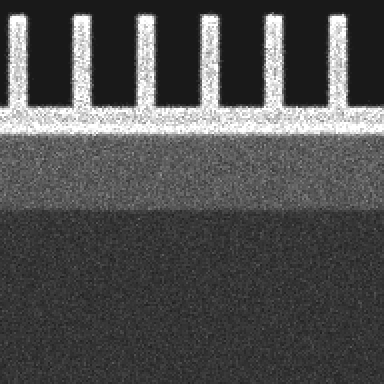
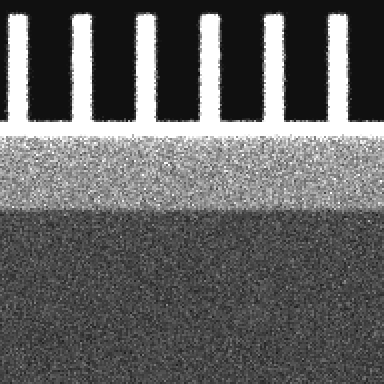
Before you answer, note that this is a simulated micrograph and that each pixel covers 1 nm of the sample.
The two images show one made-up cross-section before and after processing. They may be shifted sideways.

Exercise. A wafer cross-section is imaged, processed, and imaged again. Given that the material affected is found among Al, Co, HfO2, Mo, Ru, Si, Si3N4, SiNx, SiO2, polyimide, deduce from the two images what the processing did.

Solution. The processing removed Ru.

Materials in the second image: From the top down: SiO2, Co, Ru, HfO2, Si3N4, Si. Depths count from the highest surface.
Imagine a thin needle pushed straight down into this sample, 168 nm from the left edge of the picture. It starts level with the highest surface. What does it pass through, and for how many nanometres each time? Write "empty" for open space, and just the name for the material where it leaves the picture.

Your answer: empty 108, HfO2 10, Si3N4 76, Si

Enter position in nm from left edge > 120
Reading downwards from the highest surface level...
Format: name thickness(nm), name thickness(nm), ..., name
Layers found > empty 108, HfO2 10, Si3N4 76, Si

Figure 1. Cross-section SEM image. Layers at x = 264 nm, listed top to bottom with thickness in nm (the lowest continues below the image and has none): empty 108, HfO2 10, Si3N4 76, Si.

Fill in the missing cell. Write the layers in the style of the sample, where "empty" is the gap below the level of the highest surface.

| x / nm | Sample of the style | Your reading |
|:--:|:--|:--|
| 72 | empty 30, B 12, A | empty 108, HfO2 10, Si3N4 76, Si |